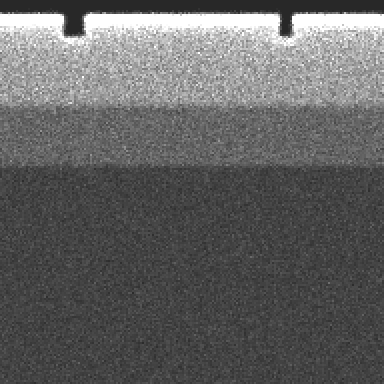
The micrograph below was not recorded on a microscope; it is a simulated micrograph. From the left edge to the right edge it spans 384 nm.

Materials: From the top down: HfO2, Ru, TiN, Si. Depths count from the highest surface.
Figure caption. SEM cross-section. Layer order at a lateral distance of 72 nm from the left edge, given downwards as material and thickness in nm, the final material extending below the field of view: empty 22, Ru 68, TiN 60, Si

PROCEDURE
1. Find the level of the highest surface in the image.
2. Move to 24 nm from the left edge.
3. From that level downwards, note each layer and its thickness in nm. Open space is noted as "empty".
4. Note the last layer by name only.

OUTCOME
HfO2 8, Ru 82, TiN 60, Si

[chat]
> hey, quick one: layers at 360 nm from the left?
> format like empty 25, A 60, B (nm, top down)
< HfO2 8, Ru 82, TiN 60, Si